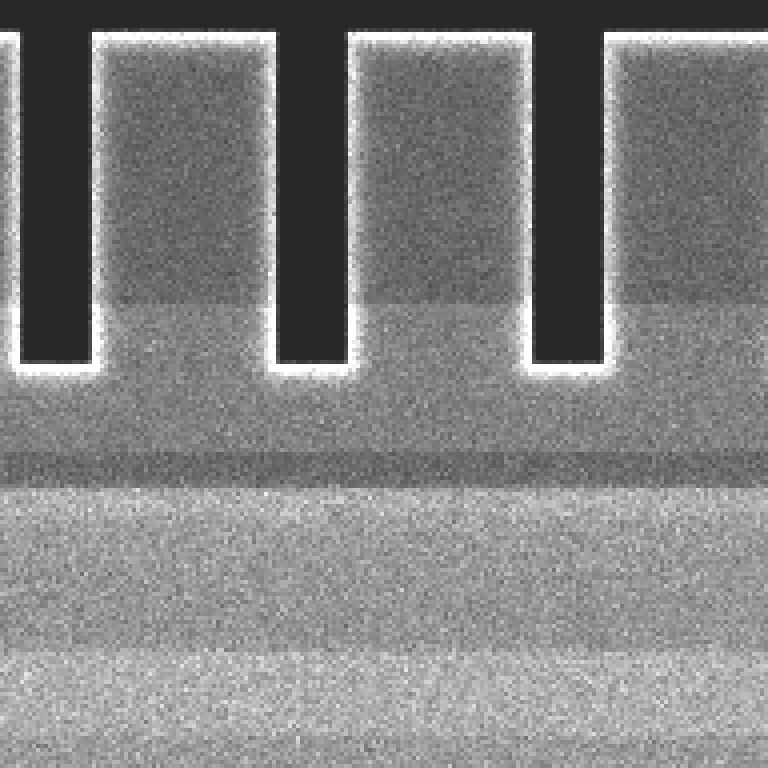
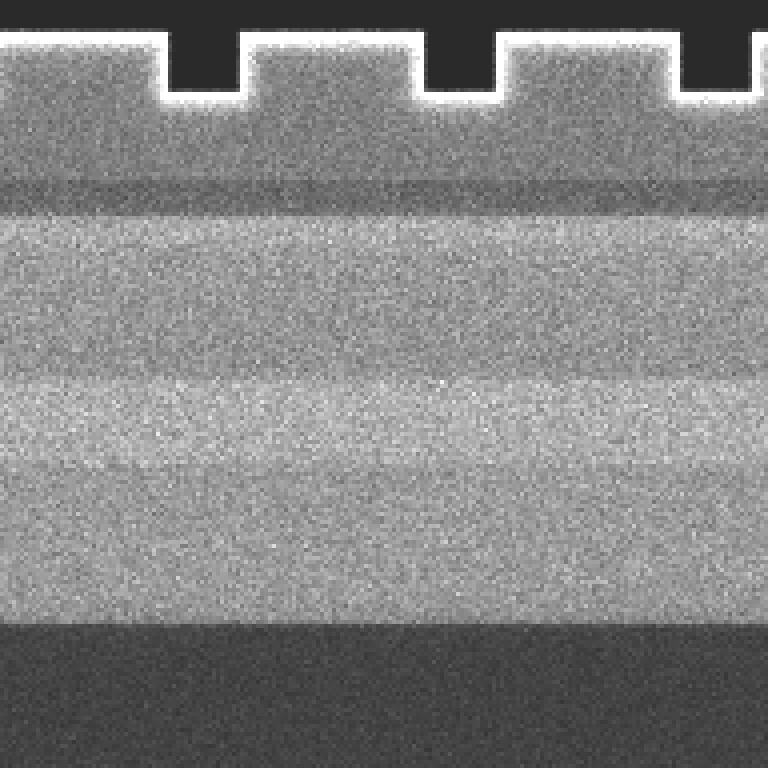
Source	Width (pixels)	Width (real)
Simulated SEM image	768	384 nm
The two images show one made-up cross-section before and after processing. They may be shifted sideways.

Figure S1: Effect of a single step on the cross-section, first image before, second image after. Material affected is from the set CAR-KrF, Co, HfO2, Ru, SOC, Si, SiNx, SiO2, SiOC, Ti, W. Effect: removed SOC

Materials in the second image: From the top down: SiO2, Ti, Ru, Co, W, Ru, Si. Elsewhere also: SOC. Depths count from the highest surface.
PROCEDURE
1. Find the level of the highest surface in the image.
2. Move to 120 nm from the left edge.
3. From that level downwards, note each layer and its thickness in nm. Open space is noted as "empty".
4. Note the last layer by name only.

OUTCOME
SiO2 74, Ti 18, Ru 14, Co 68, W 42, Ru 80, Si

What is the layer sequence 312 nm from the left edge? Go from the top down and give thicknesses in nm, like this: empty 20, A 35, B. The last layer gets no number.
SiO2 74, Ti 18, Ru 14, Co 68, W 42, Ru 80, Si